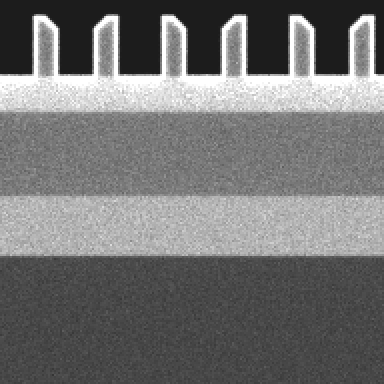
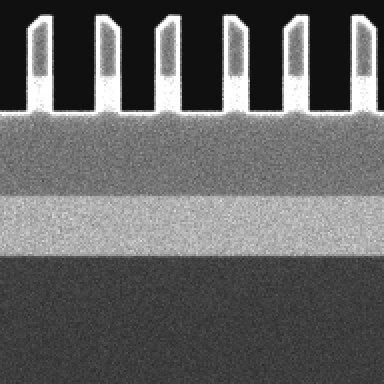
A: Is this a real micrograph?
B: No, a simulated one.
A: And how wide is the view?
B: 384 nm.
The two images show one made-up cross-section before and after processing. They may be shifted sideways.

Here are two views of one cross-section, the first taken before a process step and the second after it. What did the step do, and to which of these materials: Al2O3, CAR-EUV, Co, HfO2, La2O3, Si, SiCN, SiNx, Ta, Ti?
It removed Co.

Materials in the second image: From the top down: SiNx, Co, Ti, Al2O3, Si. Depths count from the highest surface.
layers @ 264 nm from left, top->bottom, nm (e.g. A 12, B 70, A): empty 96, Ti 84, Al2O3 60, Si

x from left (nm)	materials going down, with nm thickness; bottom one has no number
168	SiNx 60, Co 36, Ti 84, Al2O3 60, Si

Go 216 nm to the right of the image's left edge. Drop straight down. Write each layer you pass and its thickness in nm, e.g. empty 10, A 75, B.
empty 96, Ti 84, Al2O3 60, Si